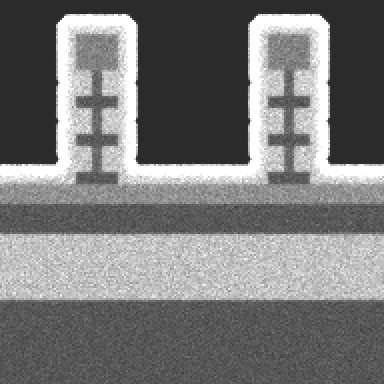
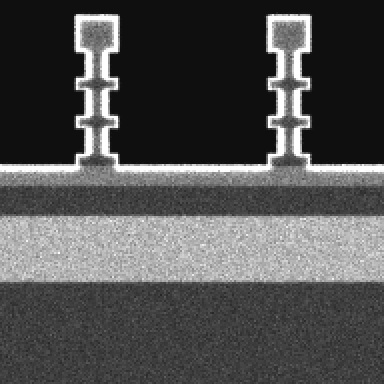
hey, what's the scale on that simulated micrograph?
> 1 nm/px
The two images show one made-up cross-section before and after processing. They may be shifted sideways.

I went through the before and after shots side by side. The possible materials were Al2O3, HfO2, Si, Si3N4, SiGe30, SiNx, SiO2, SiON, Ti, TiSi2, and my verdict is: removed, Al2O3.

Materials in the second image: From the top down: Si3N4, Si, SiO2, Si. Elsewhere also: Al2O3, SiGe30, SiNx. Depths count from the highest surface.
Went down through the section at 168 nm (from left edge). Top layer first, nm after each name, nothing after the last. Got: empty 150, Si3N4 20, Si 30, SiO2 66, Si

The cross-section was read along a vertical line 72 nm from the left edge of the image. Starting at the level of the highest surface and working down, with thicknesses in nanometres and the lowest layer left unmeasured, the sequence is empty 150, Si3N4 20, Si 30, SiO2 66, Si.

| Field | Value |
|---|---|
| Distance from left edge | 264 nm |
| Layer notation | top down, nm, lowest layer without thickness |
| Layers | empty 150, Si3N4 20, Si 30, SiO2 66, Si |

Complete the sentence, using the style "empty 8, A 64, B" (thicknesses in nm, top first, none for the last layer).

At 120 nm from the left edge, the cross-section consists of empty 150, Si3N4 20, Si 30, SiO2 66, Si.